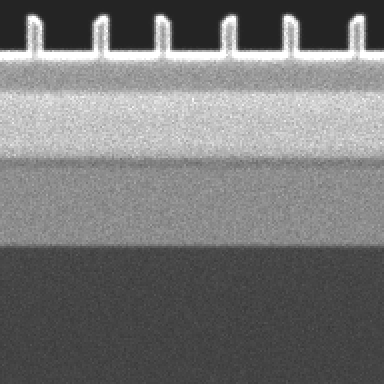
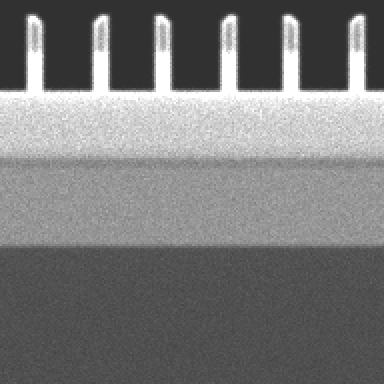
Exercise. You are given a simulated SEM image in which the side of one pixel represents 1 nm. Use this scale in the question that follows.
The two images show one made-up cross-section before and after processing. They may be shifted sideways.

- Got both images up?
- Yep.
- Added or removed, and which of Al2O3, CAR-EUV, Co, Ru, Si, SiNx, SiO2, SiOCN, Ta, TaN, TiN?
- removed, Al2O3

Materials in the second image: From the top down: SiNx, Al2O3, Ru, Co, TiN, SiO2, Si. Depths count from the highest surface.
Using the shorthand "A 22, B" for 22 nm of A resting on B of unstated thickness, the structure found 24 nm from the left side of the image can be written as empty 76, Ru 56, Co 10, TiN 10, SiO2 78, Si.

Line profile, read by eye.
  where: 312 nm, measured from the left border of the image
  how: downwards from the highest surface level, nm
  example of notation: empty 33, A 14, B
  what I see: empty 76, Ru 56, Co 10, TiN 10, SiO2 78, Si